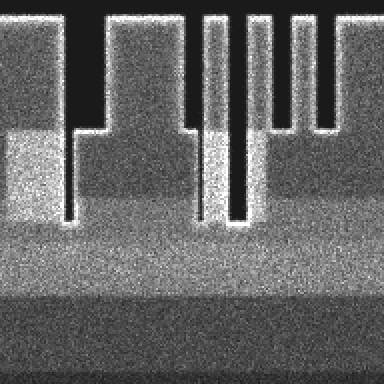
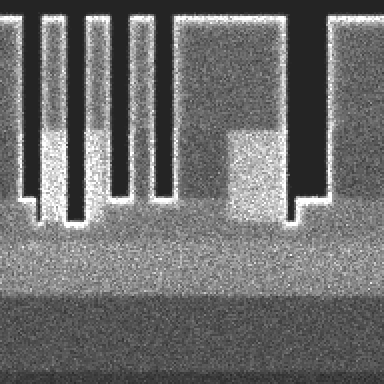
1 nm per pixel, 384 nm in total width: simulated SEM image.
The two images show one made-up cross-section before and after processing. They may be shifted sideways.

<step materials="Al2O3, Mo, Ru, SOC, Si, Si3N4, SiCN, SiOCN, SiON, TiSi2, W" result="removed Si3N4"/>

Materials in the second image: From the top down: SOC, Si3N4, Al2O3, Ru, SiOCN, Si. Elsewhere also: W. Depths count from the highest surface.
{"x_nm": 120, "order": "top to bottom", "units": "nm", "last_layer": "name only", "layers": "empty 182, Al2O3 44, Ru 54, SiOCN 76, Si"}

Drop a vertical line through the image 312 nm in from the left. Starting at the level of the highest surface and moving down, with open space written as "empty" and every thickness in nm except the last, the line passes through empty 182, Al2O3 44, Ru 54, SiOCN 76, Si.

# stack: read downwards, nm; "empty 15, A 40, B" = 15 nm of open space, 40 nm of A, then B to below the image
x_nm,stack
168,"empty 182, Al2O3 44, Ru 54, SiOCN 76, Si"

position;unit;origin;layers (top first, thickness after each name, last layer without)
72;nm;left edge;empty 206, Al2O3 20, Ru 54, SiOCN 76, Si